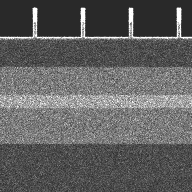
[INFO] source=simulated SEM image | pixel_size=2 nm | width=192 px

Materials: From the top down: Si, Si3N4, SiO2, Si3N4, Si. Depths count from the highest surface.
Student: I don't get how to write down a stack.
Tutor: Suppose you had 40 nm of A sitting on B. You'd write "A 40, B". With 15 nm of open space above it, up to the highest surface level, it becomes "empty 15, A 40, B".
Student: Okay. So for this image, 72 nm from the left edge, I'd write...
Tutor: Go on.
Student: Si 118, Si3N4 56, SiO2 26, Si3N4 72, Si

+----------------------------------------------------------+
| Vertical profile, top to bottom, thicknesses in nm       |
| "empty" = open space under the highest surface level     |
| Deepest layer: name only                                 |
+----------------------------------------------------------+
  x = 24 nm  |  empty 58, Si 60, Si3N4 56, SiO2 26, Si3N4 72, Si